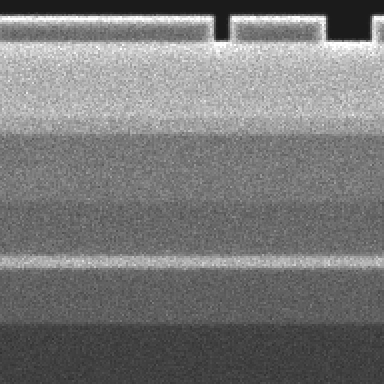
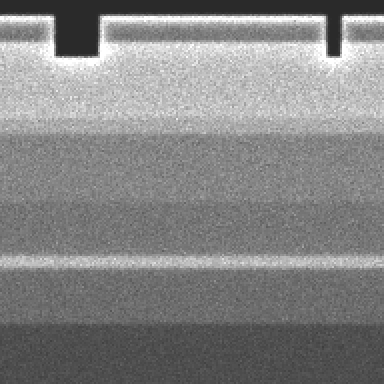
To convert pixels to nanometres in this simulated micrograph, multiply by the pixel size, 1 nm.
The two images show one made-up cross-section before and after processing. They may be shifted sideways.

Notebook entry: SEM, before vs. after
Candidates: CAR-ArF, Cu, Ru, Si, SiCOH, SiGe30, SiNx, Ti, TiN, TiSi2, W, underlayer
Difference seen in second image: W removed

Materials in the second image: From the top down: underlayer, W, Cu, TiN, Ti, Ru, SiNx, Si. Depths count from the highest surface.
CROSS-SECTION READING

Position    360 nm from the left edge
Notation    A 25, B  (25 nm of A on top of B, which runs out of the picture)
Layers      underlayer 26, W 76, Cu 16, TiN 68, Ti 54, Ru 12, SiNx 56, Si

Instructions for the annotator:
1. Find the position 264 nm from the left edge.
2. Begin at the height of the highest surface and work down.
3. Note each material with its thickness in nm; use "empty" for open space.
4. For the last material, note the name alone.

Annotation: underlayer 26, W 76, Cu 16, TiN 68, Ti 54, Ru 12, SiNx 56, Si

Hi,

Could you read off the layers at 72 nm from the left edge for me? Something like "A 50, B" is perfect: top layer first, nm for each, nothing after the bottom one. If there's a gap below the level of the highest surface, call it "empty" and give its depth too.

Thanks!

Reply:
empty 42, W 60, Cu 16, TiN 68, Ti 54, Ru 12, SiNx 56, Si